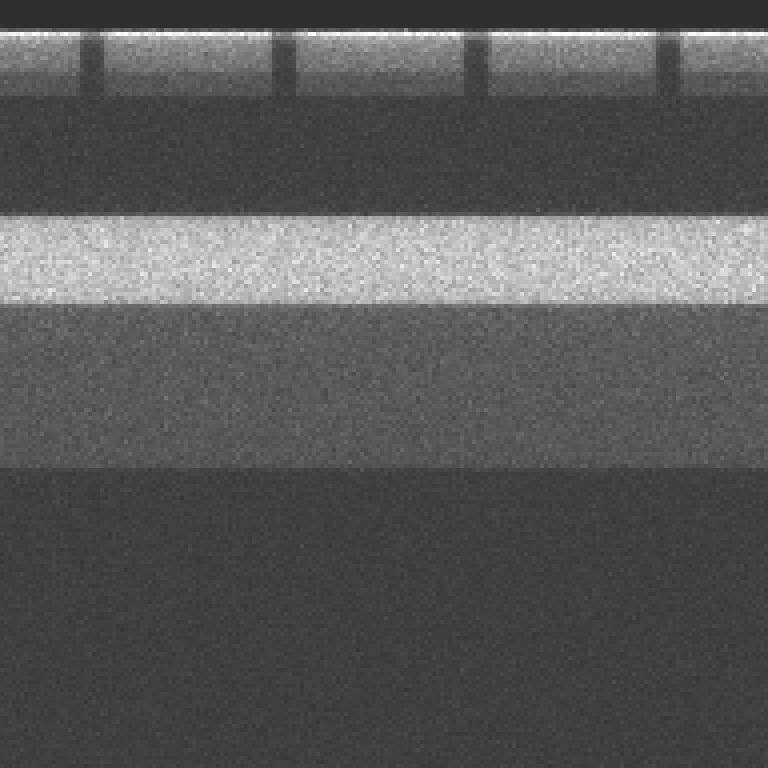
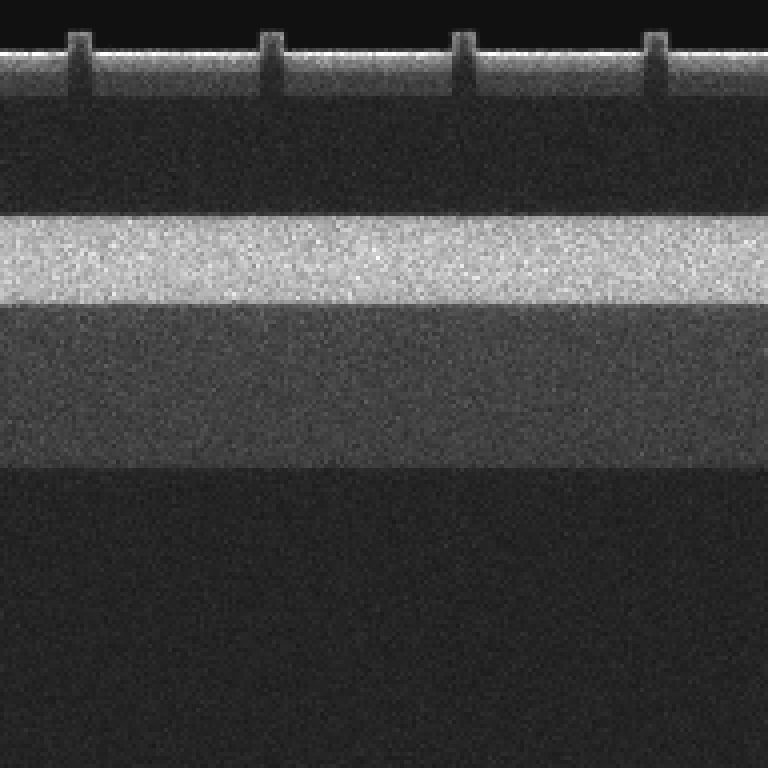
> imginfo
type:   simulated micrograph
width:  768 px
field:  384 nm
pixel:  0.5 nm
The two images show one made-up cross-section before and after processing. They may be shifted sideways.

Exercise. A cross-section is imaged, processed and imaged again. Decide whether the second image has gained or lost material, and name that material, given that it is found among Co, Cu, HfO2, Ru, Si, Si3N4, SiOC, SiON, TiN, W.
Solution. removed: Co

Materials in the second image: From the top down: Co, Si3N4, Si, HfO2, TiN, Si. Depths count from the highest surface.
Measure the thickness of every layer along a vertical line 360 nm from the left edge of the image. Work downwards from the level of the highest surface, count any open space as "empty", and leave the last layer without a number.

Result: empty 10, Co 10, Si3N4 12, Si 60, HfO2 44, TiN 82, Si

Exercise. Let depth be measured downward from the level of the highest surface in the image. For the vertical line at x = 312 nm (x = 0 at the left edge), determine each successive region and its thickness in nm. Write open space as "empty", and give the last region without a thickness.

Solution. empty 10, Co 10, Si3N4 12, Si 60, HfO2 44, TiN 82, Si